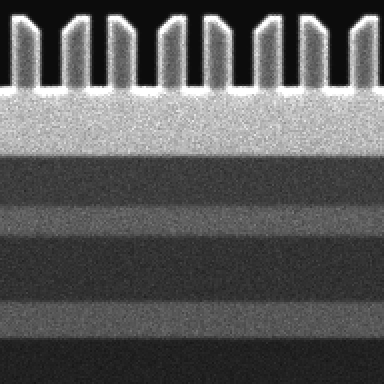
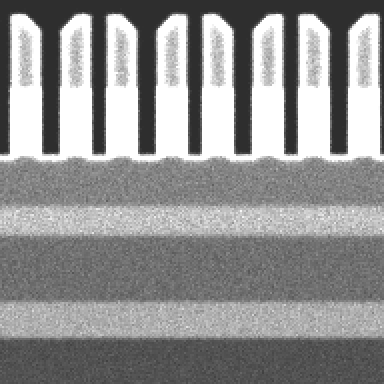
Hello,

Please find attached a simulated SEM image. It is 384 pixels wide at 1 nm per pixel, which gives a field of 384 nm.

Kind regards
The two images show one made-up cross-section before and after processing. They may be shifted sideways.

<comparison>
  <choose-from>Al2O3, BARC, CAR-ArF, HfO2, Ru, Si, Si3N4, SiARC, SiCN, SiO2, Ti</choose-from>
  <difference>HfO2 removed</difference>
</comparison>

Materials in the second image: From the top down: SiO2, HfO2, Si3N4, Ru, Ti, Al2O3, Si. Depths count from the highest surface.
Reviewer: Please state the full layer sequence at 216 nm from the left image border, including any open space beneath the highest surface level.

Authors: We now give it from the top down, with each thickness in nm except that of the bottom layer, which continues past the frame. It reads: SiO2 72, HfO2 68, Si3N4 50, Ru 30, Ti 66, Al2O3 36, Si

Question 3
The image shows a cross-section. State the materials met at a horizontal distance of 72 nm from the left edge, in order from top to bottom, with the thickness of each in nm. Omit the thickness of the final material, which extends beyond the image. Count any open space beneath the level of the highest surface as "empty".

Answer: empty 4, SiO2 68, HfO2 68, Si3N4 50, Ru 30, Ti 66, Al2O3 36, Si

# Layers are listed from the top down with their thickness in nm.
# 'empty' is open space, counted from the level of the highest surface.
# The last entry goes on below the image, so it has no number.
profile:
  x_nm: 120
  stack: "SiO2 72, HfO2 68, Si3N4 50, Ru 30, Ti 66, Al2O3 36, Si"